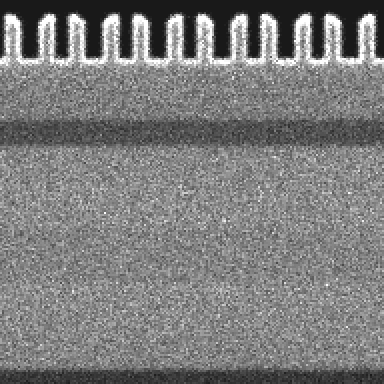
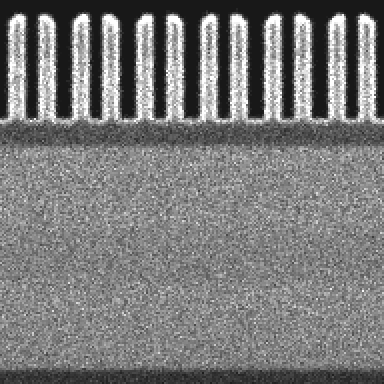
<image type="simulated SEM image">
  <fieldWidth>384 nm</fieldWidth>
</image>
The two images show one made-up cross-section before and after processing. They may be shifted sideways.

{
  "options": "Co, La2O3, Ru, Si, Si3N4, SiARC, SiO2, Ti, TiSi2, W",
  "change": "removed",
  "material": "Co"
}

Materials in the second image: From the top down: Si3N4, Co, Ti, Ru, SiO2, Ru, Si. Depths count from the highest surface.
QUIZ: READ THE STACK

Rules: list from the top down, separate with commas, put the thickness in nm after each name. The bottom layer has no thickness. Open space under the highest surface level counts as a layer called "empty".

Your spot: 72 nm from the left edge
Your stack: empty 104, Ti 26, Ru 84, SiO2 52, Ru 88, Si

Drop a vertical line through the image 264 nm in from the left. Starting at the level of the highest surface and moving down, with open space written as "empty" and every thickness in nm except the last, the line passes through empty 104, Ti 26, Ru 84, SiO2 52, Ru 88, Si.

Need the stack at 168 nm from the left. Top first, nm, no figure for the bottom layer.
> Si3N4 44, Co 60, Ti 26, Ru 84, SiO2 52, Ru 88, Si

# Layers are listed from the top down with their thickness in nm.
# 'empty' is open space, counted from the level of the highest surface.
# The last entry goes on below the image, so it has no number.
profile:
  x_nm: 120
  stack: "empty 104, Ti 26, Ru 84, SiO2 52, Ru 88, Si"